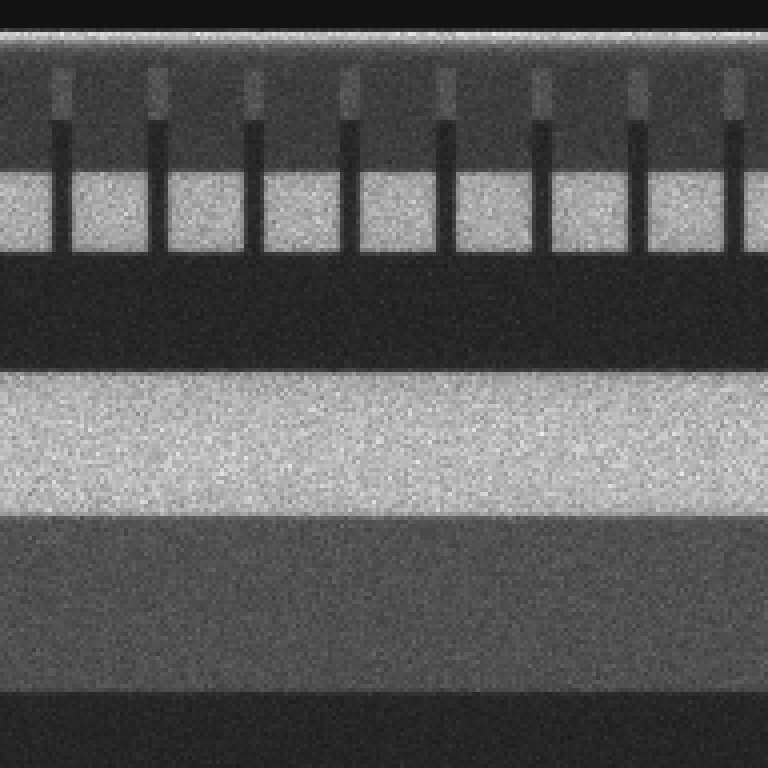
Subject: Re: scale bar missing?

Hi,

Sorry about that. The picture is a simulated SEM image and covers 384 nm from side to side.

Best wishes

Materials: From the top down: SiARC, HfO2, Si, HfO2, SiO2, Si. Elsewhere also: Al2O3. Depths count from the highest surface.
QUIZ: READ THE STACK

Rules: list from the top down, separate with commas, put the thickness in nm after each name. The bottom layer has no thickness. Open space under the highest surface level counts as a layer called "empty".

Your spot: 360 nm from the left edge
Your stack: SiARC 70, HfO2 40, Si 60, HfO2 72, SiO2 88, Si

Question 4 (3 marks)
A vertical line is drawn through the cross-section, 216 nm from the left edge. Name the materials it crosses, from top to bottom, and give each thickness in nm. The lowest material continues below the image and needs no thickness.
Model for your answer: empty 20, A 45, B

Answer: SiARC 70, HfO2 40, Si 60, HfO2 72, SiO2 88, Si